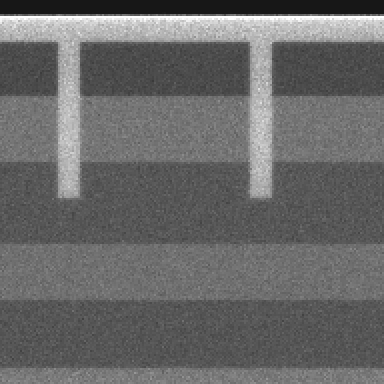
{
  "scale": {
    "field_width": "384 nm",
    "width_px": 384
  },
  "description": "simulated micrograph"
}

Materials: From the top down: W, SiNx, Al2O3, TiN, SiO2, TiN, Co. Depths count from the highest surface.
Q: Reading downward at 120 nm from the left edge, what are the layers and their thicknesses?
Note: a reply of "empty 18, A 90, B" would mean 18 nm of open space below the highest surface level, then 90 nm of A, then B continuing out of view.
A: W 26, SiNx 54, Al2O3 66, TiN 82, SiO2 56, TiN 68, Co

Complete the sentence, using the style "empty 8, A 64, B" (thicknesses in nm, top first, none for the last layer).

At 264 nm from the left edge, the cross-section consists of W 182, TiN 46, SiO2 56, TiN 68, Co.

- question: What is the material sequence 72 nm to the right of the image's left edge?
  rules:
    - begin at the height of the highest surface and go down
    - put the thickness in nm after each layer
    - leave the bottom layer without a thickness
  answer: W 182, TiN 46, SiO2 56, TiN 68, Co